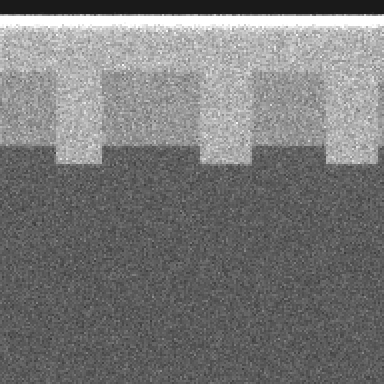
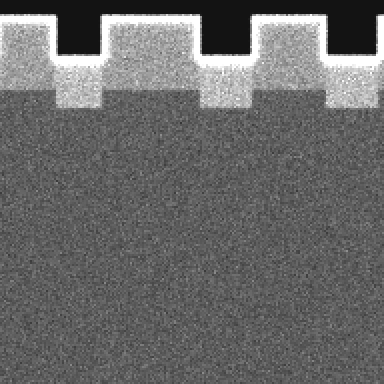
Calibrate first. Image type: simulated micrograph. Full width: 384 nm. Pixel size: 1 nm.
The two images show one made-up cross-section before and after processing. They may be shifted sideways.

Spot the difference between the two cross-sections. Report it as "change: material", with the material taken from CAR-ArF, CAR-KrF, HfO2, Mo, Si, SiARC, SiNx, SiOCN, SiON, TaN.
removed: SiARC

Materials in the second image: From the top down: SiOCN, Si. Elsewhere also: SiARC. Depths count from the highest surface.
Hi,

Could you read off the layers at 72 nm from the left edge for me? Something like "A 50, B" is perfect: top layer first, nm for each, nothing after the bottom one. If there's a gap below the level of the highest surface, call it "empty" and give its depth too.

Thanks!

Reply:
empty 40, SiARC 52, Si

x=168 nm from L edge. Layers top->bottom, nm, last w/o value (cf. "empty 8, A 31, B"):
SiOCN 74, Si